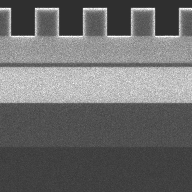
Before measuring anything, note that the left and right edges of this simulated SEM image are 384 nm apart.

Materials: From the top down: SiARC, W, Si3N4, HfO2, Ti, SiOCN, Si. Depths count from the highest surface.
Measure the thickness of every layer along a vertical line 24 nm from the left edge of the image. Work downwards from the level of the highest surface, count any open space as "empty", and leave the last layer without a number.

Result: empty 56, W 54, Si3N4 8, HfO2 72, Ti 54, SiOCN 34, Si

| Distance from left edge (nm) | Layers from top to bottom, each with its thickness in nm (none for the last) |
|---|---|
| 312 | empty 56, W 54, Si3N4 8, HfO2 72, Ti 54, SiOCN 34, Si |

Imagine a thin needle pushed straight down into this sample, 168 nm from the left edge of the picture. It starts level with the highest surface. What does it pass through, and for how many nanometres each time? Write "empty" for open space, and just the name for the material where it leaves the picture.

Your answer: SiARC 56, W 54, Si3N4 8, HfO2 72, Ti 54, SiOCN 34, Si